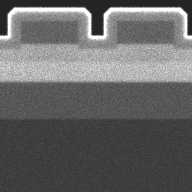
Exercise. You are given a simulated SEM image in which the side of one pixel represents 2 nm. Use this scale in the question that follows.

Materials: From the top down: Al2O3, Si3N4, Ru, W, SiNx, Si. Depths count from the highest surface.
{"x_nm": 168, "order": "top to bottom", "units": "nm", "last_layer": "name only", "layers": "Al2O3 82, Ru 26, W 40, SiNx 74, Si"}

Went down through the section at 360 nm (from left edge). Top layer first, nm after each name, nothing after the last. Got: Al2O3 82, Ru 26, W 40, SiNx 74, Si